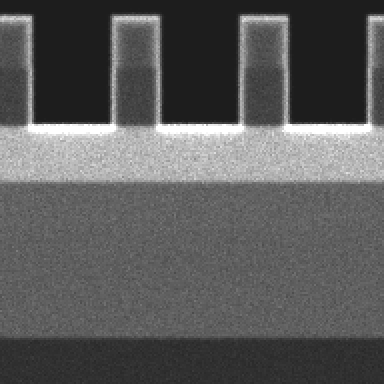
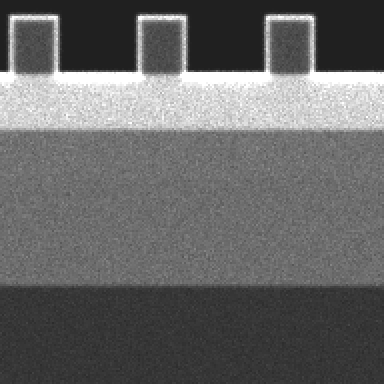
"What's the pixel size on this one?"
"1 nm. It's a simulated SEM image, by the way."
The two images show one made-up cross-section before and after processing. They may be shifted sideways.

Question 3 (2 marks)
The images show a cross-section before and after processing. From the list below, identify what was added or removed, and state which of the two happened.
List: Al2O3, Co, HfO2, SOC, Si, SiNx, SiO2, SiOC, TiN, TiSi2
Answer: SOC was removed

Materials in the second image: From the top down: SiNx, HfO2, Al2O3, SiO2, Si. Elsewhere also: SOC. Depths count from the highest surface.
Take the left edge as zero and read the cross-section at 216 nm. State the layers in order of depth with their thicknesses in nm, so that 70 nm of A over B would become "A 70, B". empty 58, HfO2 56, Al2O3 48, SiO2 108, Si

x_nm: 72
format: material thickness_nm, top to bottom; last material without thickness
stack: empty 58, HfO2 56, Al2O3 48, SiO2 108, Si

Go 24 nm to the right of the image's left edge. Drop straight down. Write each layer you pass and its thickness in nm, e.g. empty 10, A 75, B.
SiNx 58, HfO2 56, Al2O3 48, SiO2 108, Si